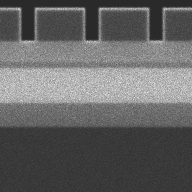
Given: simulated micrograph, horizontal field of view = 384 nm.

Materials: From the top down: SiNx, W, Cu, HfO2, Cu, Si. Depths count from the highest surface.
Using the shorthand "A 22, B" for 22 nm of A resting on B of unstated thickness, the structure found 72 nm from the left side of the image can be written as SiNx 66, W 42, Cu 12, HfO2 70, Cu 48, Si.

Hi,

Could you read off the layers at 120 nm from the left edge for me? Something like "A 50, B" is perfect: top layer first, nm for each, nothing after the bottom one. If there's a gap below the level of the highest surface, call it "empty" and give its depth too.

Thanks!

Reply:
SiNx 66, W 42, Cu 12, HfO2 70, Cu 48, Si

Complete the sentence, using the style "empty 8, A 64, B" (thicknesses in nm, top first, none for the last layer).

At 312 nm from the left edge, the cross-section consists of empty 66, W 42, Cu 12, HfO2 70, Cu 48, Si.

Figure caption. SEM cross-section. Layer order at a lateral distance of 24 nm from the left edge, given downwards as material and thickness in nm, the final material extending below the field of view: SiNx 66, W 42, Cu 12, HfO2 70, Cu 48, Si